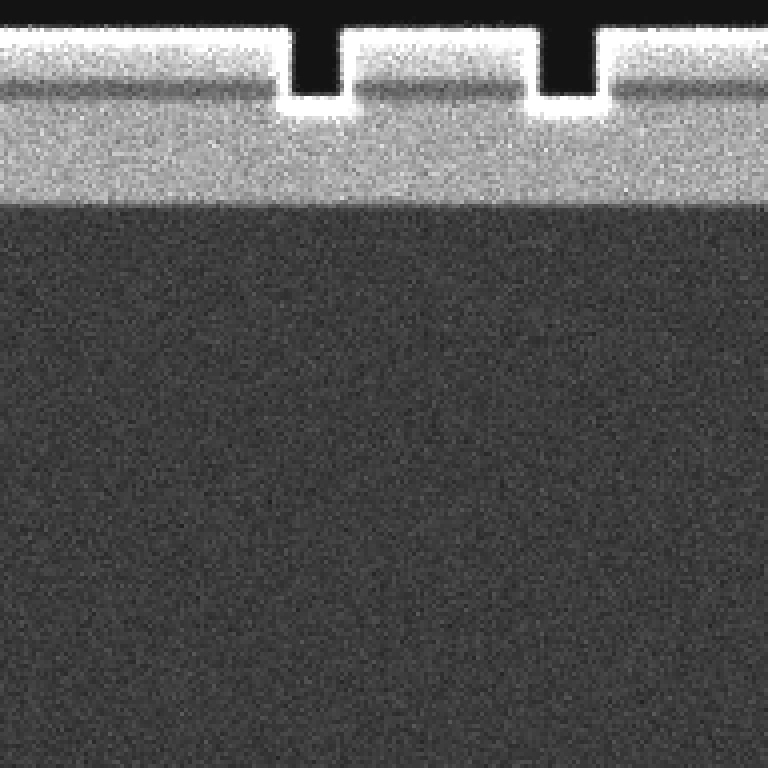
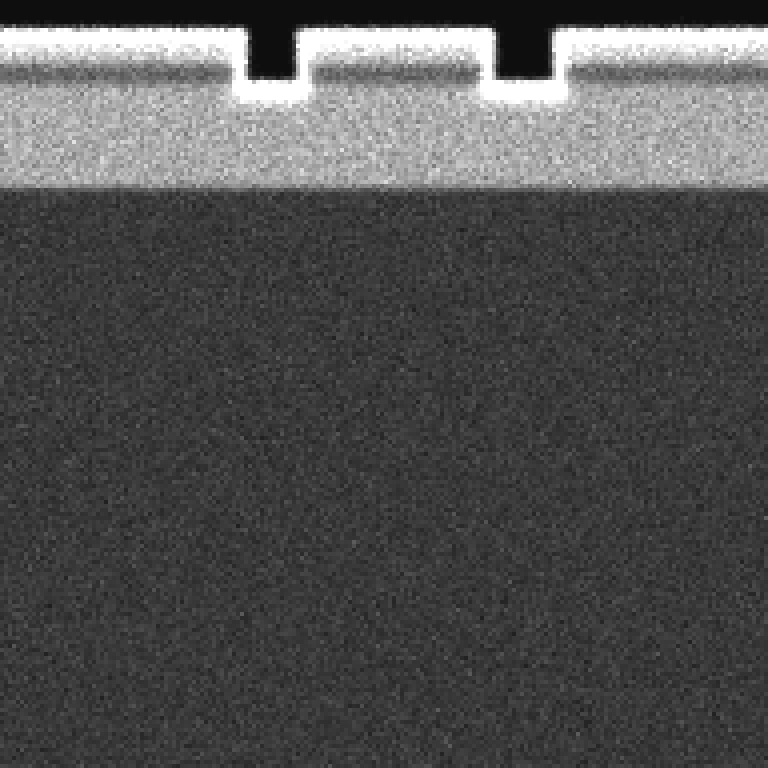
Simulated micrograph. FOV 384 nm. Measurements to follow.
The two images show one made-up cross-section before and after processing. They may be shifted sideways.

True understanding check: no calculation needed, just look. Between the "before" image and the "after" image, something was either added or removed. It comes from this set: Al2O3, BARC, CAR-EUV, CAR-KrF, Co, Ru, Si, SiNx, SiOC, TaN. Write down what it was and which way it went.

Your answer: Ru (removed)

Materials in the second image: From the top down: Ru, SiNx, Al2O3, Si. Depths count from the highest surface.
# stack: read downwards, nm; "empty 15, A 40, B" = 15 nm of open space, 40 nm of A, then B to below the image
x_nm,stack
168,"Ru 16, SiNx 10, Al2O3 52, Si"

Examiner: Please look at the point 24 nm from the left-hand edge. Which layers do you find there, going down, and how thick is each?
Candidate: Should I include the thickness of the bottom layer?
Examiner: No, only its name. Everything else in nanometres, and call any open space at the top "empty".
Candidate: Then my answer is Ru 16, SiNx 10, Al2O3 52, Si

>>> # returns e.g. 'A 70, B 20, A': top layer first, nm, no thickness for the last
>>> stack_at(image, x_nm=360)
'Ru 16, SiNx 10, Al2O3 52, Si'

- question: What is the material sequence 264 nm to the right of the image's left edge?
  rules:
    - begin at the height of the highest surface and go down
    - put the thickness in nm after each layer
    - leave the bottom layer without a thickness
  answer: empty 26, Al2O3 52, Si